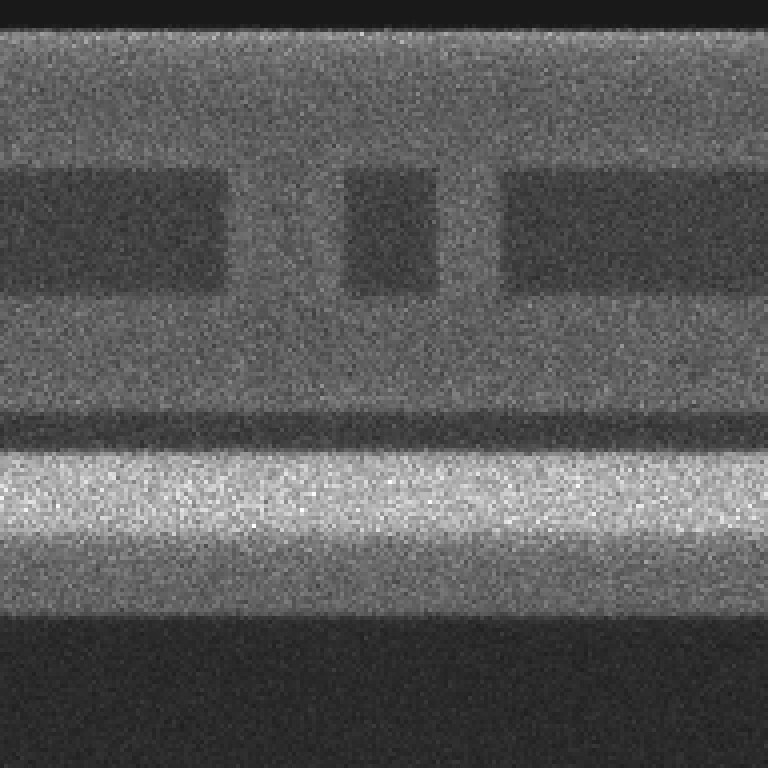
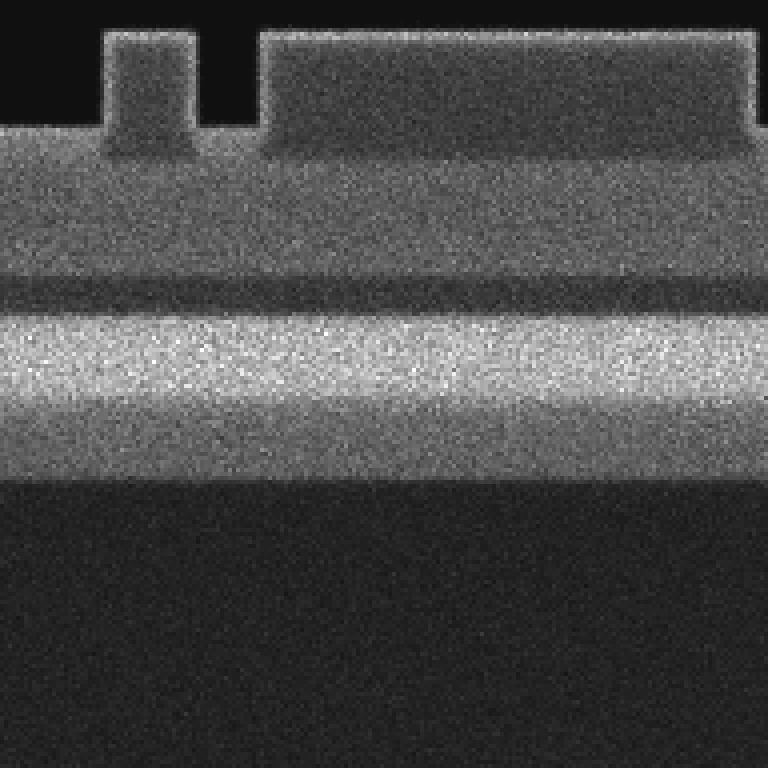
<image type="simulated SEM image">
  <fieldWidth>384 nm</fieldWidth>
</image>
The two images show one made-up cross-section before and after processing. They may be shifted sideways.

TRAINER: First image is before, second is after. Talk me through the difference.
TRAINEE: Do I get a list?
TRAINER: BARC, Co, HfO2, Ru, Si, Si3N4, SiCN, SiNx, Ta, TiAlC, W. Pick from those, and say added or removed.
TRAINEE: removed: Ru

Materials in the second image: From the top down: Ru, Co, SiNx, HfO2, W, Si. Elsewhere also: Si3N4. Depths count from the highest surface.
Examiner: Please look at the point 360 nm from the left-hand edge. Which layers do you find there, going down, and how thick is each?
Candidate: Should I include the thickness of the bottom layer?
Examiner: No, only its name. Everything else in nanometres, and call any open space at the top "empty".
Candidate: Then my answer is Si3N4 64, Co 58, SiNx 20, HfO2 40, W 42, Si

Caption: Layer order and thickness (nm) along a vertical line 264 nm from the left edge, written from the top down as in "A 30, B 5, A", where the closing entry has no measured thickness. Si3N4 64, Co 58, SiNx 20, HfO2 40, W 42, Si